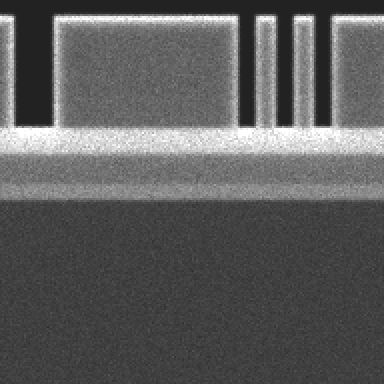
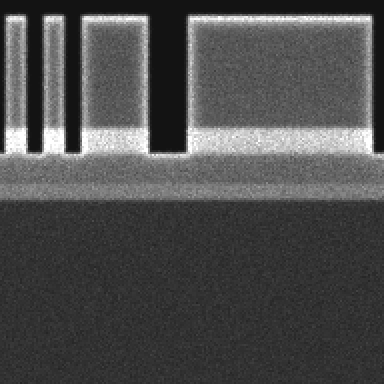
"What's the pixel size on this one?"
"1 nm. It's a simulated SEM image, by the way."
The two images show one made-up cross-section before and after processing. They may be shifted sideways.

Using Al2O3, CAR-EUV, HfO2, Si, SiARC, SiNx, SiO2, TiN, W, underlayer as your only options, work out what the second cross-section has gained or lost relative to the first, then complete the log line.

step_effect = removed W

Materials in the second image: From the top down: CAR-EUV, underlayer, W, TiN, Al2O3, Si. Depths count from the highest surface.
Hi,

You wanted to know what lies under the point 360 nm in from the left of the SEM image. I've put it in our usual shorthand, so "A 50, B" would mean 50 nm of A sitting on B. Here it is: CAR-EUV 80, underlayer 32, W 26, TiN 30, Al2O3 16, Si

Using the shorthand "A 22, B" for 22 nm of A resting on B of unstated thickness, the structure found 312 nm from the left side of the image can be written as CAR-EUV 80, underlayer 32, W 26, TiN 30, Al2O3 16, Si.